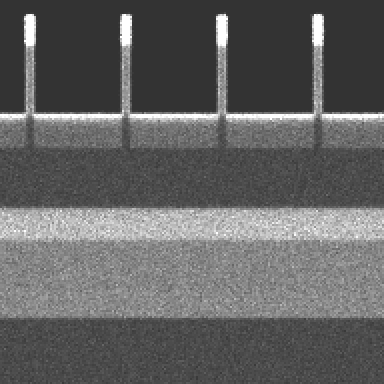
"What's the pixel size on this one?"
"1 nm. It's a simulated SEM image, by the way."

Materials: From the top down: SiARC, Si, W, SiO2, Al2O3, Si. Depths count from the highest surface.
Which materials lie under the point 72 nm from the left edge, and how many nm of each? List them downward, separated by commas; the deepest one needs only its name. empty 98, SiARC 34, Si 60, W 32, SiO2 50, Al2O3 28, Si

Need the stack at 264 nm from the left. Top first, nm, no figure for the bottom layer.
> empty 98, SiARC 34, Si 60, W 32, SiO2 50, Al2O3 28, Si